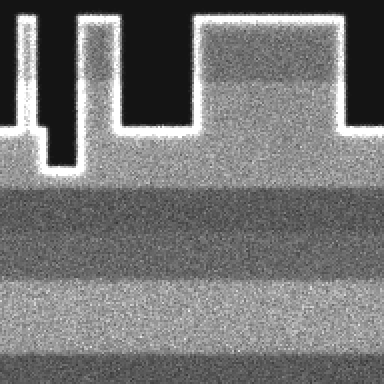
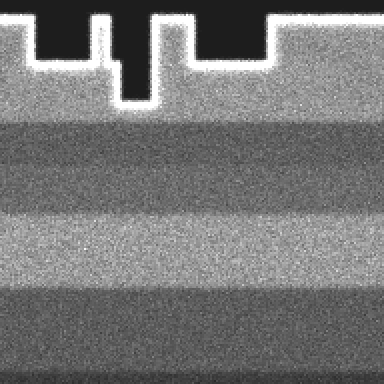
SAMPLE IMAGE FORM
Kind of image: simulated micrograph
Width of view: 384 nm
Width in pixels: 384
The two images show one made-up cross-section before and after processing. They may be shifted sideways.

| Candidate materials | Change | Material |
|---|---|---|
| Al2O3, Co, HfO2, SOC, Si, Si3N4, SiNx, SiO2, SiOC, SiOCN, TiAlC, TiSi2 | removed | SOC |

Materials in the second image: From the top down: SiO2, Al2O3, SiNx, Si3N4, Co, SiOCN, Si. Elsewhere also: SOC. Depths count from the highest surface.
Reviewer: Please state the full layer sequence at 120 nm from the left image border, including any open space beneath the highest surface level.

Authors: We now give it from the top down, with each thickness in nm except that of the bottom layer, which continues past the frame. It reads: empty 86, Al2O3 20, SiNx 44, Si3N4 48, Co 74, SiOCN 84, Si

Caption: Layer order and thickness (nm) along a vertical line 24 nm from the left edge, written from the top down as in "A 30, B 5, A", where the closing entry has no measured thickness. SiO2 46, Al2O3 60, SiNx 44, Si3N4 48, Co 74, SiOCN 84, Si